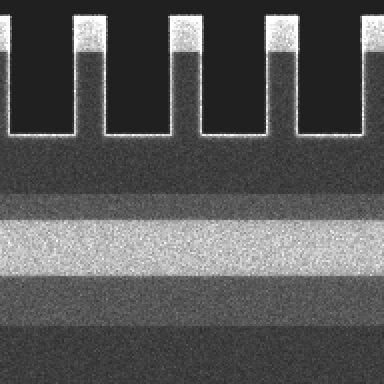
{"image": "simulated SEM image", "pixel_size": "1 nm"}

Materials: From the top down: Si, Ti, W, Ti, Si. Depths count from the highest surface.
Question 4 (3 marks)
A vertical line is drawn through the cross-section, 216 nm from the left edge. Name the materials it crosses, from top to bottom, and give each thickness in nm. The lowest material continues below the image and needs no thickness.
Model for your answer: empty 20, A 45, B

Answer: empty 118, Si 60, Ti 26, W 56, Ti 50, Si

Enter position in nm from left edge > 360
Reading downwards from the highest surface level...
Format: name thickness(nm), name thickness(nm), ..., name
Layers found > empty 118, Si 60, Ti 26, W 56, Ti 50, Si